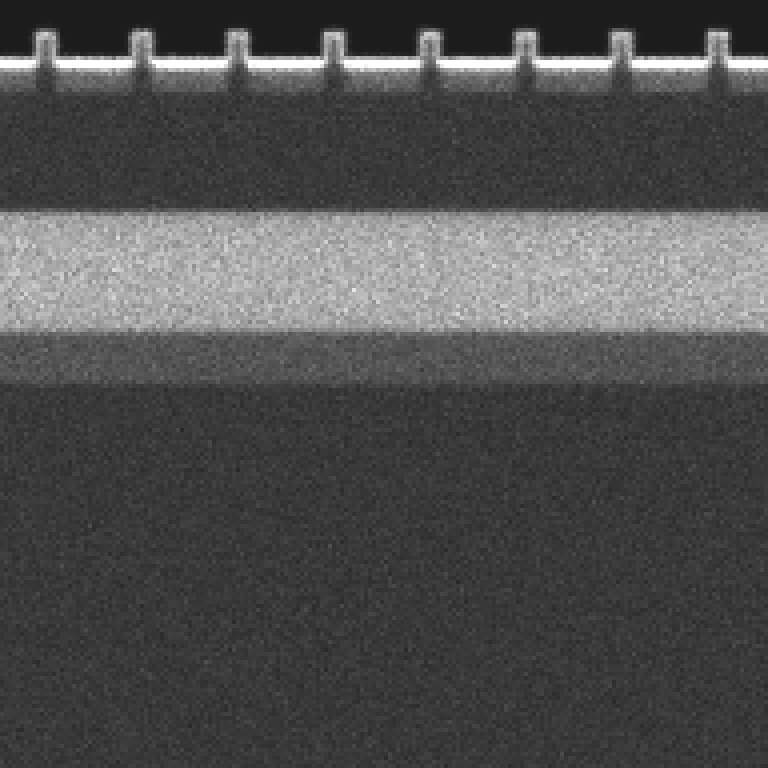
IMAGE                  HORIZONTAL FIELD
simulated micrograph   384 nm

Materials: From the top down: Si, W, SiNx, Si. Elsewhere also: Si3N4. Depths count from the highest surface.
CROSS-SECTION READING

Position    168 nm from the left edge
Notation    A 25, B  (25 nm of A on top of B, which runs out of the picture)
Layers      Si 90, W 60, SiNx 26, Si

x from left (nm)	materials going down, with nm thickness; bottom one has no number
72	Si 90, W 60, SiNx 26, Si